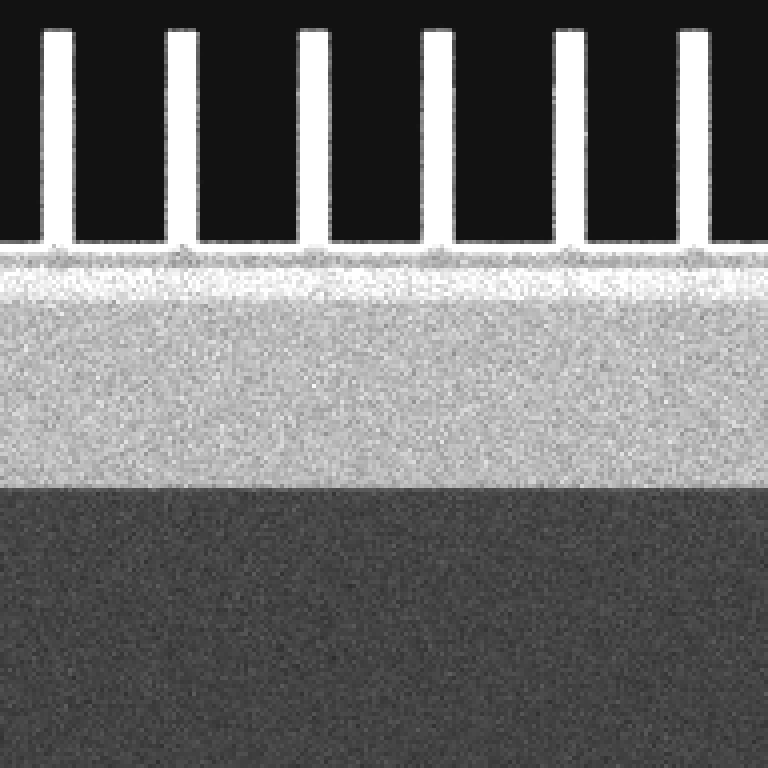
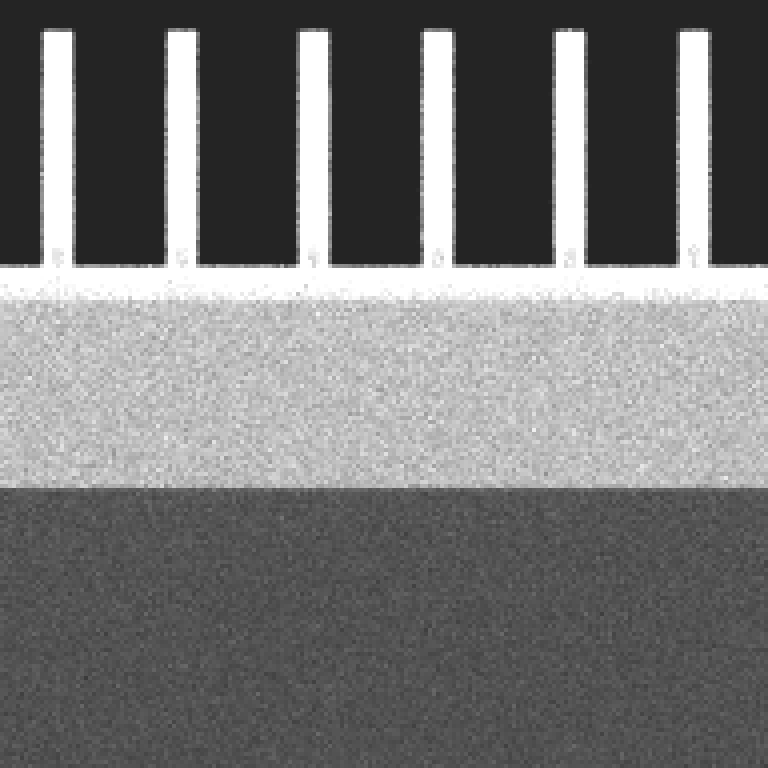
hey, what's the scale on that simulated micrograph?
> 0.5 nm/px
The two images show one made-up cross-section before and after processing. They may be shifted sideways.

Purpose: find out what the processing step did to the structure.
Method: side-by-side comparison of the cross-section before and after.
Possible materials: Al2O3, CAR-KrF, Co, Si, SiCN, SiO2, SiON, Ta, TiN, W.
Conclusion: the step removed TiN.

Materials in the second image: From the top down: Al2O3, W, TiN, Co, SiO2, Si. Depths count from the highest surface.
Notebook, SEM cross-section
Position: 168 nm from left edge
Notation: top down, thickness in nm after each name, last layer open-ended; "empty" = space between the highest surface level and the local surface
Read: empty 118, Co 16, SiO2 94, Si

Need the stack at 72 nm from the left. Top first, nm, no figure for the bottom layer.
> empty 118, Co 16, SiO2 94, Si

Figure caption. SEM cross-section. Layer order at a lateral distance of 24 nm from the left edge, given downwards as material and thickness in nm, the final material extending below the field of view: Al2O3 28, W 78, TiN 12, Co 16, SiO2 94, Si